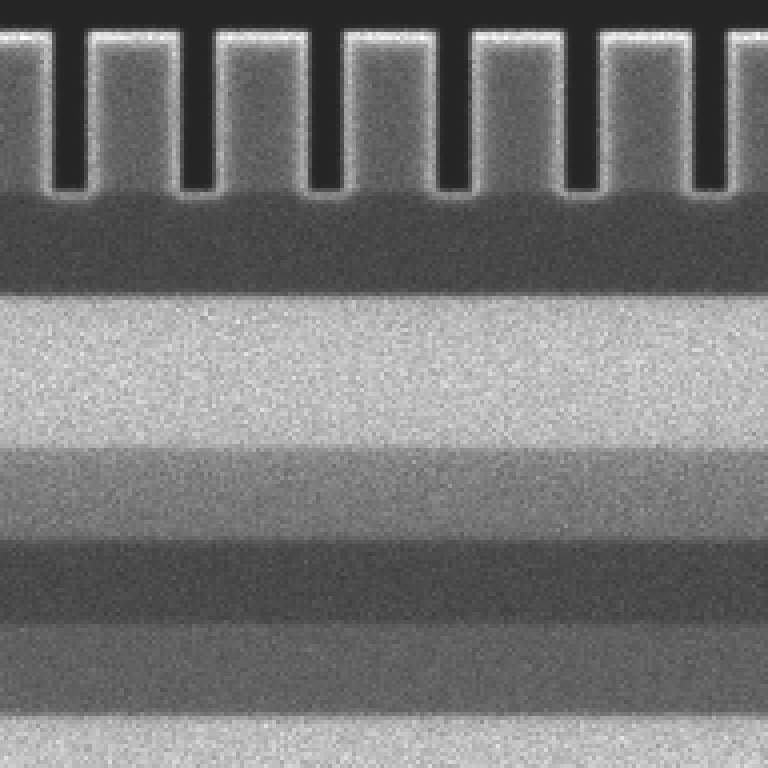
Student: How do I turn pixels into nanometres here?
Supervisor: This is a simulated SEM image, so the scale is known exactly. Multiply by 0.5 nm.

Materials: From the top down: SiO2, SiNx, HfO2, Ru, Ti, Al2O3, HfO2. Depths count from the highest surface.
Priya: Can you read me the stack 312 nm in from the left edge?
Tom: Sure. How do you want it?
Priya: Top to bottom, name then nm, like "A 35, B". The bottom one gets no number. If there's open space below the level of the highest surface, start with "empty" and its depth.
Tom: SiO2 80, SiNx 52, HfO2 76, Ru 46, Ti 42, Al2O3 46, HfO2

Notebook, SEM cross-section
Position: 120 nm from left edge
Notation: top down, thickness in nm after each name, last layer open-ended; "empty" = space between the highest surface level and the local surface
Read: SiO2 80, SiNx 52, HfO2 76, Ru 46, Ti 42, Al2O3 46, HfO2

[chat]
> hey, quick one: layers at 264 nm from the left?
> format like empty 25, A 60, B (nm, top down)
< SiO2 80, SiNx 52, HfO2 76, Ru 46, Ti 42, Al2O3 46, HfO2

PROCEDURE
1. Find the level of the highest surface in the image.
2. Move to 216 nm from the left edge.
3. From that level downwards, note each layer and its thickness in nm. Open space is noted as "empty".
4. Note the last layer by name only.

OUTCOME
SiO2 80, SiNx 52, HfO2 76, Ru 46, Ti 42, Al2O3 46, HfO2